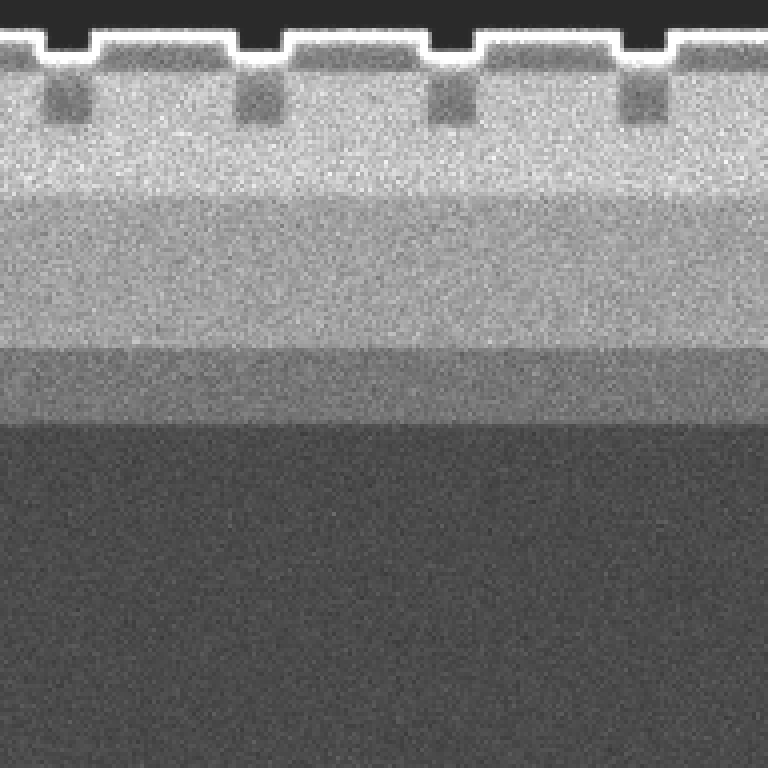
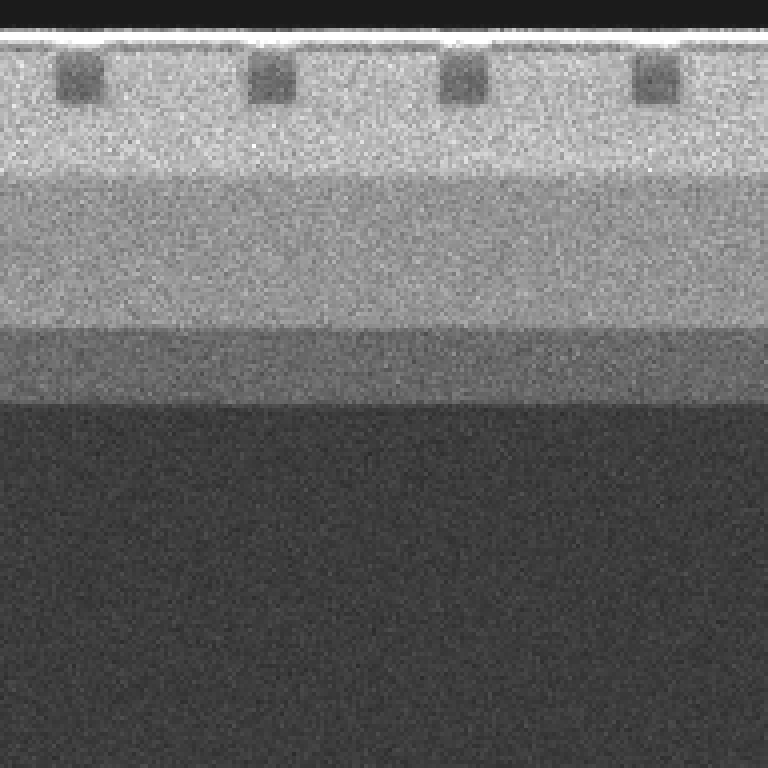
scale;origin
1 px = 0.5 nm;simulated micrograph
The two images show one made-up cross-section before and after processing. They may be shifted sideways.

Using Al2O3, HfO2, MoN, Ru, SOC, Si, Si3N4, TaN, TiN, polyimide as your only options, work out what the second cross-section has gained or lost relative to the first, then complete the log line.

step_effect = removed Si3N4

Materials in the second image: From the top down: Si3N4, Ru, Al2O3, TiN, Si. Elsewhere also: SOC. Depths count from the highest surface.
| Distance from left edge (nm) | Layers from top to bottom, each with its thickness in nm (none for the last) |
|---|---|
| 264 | Si3N4 10, Ru 62, Al2O3 76, TiN 38, Si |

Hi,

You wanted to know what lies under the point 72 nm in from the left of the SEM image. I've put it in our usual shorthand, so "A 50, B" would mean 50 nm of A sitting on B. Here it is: Si3N4 10, Ru 62, Al2O3 76, TiN 38, Si